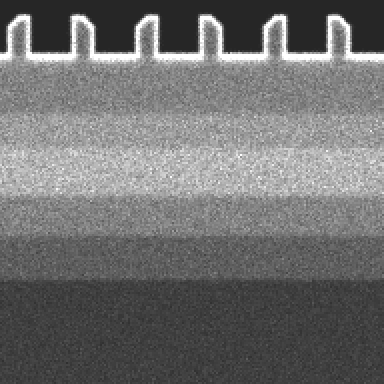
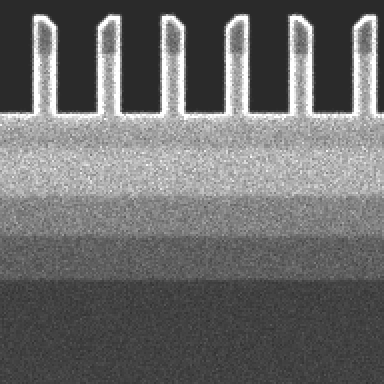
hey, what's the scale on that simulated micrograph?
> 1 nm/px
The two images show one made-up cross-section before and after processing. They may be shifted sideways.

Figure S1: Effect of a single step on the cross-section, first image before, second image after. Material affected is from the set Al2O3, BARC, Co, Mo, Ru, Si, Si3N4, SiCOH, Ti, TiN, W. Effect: removed Al2O3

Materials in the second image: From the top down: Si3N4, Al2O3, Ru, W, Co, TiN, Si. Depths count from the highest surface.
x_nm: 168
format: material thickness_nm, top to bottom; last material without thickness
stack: Si3N4 38, Al2O3 60, Ru 34, W 48, Co 40, TiN 44, Si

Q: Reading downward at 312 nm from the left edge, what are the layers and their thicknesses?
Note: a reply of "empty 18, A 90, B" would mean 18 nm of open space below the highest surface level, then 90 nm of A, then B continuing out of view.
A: empty 98, Ru 34, W 48, Co 40, TiN 44, Si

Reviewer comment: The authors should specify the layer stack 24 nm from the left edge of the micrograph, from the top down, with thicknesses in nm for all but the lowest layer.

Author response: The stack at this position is empty 98, Ru 34, W 48, Co 40, TiN 44, Si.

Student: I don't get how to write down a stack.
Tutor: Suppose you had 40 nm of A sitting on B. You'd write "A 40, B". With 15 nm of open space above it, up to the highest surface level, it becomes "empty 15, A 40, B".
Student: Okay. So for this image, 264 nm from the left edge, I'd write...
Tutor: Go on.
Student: empty 98, Ru 34, W 48, Co 40, TiN 44, Si